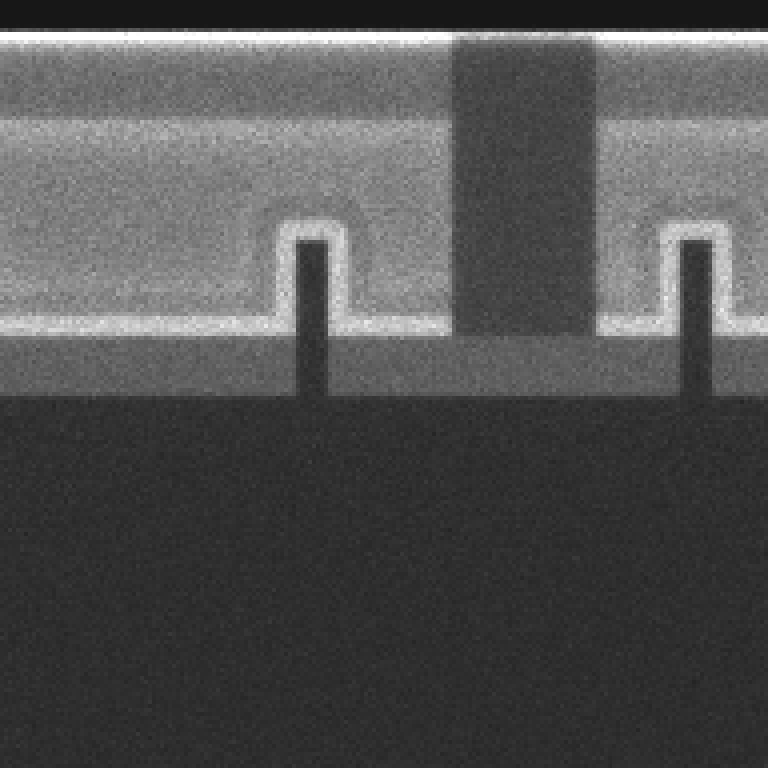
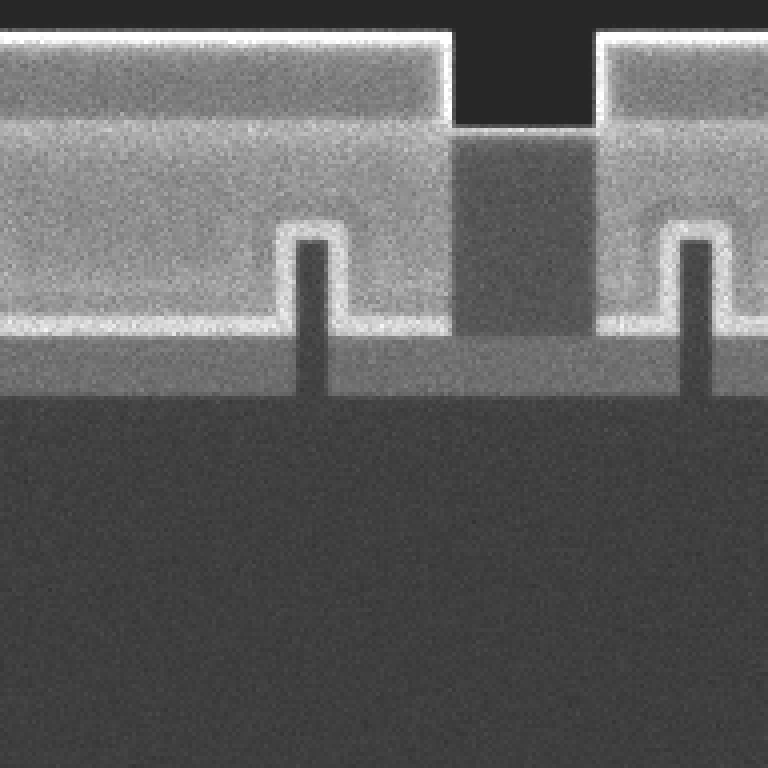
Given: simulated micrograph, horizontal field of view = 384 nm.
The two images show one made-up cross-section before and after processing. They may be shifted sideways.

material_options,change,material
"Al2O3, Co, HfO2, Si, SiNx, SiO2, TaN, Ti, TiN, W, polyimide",removed,SiNx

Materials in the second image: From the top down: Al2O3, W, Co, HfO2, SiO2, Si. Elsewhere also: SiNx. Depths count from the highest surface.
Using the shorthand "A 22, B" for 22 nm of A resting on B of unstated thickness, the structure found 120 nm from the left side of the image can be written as Al2O3 44, W 86, Co 12, HfO2 10, SiO2 30, Si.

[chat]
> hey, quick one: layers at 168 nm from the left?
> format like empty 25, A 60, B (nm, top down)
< Al2O3 44, W 38, Co 12, HfO2 58, SiO2 30, Si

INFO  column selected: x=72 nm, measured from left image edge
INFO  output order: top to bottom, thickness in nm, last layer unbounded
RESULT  Al2O3 44, W 86, Co 12, HfO2 10, SiO2 30, Si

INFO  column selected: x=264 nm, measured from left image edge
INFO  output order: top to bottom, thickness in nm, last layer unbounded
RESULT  empty 48, SiNx 104, SiO2 30, Si